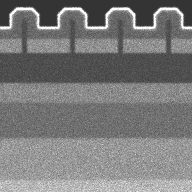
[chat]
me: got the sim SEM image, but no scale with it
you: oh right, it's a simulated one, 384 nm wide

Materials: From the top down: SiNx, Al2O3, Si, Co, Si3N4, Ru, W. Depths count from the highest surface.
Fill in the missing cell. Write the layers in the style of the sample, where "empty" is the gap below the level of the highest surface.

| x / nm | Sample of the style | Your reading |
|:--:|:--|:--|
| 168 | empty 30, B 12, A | empty 8, SiNx 54, Al2O3 28, Si 60, Co 40, Si3N4 70, Ru 84, W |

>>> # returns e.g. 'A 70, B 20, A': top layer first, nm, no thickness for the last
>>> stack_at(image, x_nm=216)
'empty 8, SiNx 54, Al2O3 28, Si 60, Co 40, Si3N4 70, Ru 84, W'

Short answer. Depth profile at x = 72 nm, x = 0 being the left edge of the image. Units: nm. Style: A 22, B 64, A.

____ empty 8, SiNx 54, Al2O3 28, Si 60, Co 40, Si3N4 70, Ru 84, W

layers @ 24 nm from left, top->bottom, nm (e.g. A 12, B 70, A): empty 8, SiNx 54, Al2O3 28, Si 60, Co 40, Si3N4 70, Ru 84, W